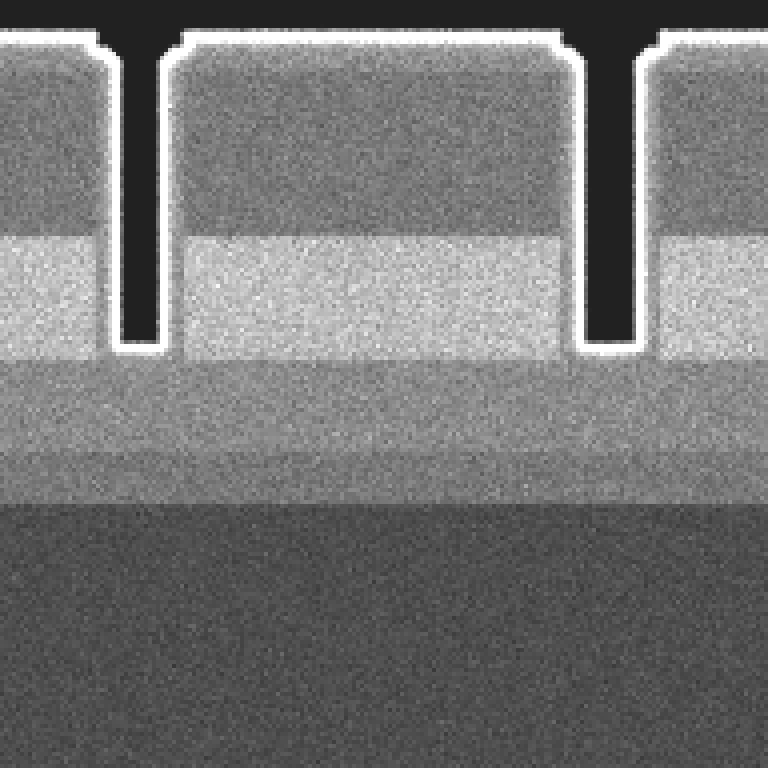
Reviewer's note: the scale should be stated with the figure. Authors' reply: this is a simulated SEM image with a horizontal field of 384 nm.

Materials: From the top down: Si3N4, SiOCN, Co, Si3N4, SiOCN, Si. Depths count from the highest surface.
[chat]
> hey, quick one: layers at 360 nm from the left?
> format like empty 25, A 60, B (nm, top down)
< Si3N4 20, SiOCN 82, Co 62, Si3N4 46, SiOCN 26, Si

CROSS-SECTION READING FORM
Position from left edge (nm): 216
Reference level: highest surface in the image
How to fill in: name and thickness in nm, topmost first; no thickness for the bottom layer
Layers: Si3N4 20, SiOCN 82, Co 62, Si3N4 46, SiOCN 26, Si